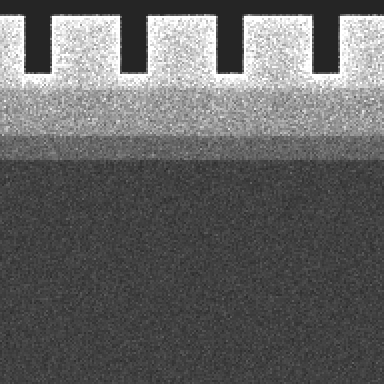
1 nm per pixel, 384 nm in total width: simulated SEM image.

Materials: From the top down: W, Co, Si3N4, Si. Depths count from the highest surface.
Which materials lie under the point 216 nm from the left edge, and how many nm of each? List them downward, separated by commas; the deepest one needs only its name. empty 58, W 14, Co 48, Si3N4 24, Si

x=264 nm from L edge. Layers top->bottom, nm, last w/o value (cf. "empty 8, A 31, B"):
W 72, Co 48, Si3N4 24, Si